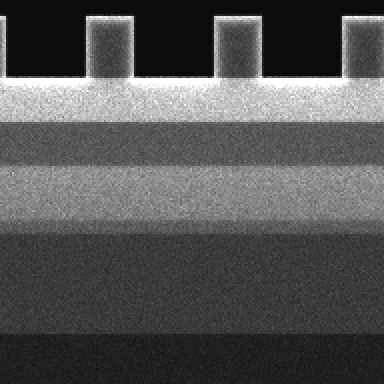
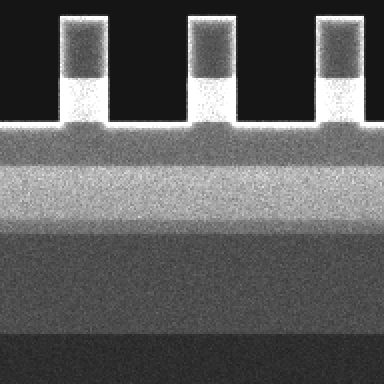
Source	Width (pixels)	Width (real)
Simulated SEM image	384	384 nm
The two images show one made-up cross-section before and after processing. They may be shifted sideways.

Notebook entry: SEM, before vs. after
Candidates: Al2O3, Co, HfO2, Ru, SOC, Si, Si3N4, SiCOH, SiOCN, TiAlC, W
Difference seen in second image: HfO2 removed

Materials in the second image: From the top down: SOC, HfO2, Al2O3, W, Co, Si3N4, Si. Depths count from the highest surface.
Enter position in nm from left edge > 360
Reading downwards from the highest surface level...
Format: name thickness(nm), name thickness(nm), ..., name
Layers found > SOC 62, HfO2 44, Al2O3 44, W 54, Co 14, Si3N4 100, Si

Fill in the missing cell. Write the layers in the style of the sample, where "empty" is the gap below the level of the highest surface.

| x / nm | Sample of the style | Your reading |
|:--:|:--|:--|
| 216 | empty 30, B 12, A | SOC 62, HfO2 44, Al2O3 44, W 54, Co 14, Si3N4 100, Si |